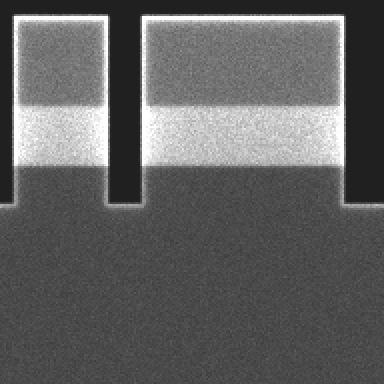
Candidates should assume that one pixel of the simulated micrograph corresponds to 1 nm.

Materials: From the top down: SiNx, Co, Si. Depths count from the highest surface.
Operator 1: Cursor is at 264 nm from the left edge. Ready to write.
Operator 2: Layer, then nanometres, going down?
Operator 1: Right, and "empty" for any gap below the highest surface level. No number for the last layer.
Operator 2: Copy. SiNx 90, Co 60, Si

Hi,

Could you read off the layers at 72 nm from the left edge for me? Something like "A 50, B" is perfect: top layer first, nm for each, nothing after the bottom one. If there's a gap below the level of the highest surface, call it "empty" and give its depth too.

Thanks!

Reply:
SiNx 90, Co 60, Si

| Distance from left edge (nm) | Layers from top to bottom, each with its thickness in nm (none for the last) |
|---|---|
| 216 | SiNx 90, Co 60, Si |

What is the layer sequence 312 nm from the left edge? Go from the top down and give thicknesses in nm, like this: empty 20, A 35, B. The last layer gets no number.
SiNx 90, Co 60, Si